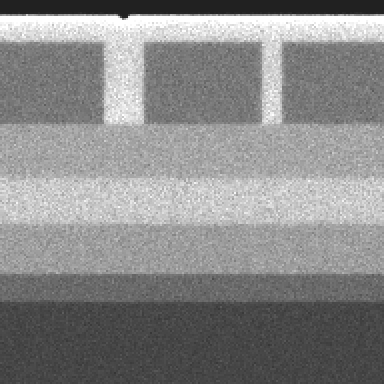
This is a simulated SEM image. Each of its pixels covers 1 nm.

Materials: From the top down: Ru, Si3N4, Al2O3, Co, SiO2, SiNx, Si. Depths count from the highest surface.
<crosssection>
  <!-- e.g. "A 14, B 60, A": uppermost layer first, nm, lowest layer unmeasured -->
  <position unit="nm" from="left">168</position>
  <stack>Ru 26, Si3N4 82, Al2O3 54, Co 46, SiO2 50, SiNx 28, Si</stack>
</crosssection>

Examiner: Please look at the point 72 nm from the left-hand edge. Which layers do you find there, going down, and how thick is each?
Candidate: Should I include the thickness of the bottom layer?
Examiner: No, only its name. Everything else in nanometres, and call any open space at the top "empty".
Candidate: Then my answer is Ru 26, Si3N4 82, Al2O3 54, Co 46, SiO2 50, SiNx 28, Si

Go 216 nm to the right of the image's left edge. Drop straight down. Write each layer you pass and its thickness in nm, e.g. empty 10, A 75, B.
Ru 26, Si3N4 82, Al2O3 54, Co 46, SiO2 50, SiNx 28, Si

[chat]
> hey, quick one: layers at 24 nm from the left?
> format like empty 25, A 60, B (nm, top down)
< Ru 26, Si3N4 82, Al2O3 54, Co 46, SiO2 50, SiNx 28, Si